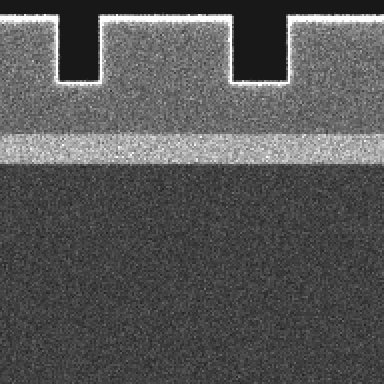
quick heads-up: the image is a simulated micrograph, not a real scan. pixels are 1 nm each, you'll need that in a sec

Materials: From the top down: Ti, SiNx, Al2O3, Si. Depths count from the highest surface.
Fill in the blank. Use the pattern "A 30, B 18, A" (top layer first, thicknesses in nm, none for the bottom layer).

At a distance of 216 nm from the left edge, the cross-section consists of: Ti 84, SiNx 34, Al2O3 30, Si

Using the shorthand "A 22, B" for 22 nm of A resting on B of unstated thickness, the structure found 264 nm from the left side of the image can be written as empty 66, Ti 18, SiNx 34, Al2O3 30, Si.